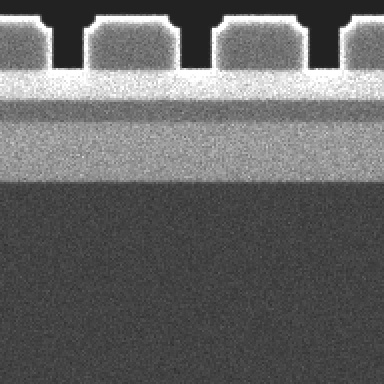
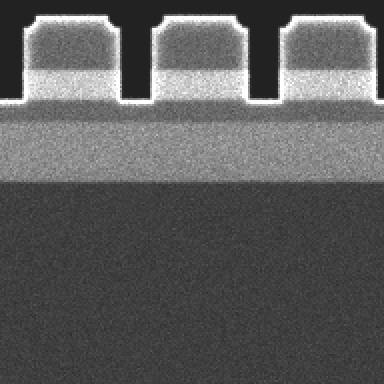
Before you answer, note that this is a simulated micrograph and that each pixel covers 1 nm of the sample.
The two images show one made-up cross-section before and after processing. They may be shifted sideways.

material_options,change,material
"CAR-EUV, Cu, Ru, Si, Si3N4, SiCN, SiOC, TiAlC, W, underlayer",removed,W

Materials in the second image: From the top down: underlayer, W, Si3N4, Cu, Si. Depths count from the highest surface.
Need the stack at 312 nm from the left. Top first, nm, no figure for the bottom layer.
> underlayer 54, W 30, Si3N4 22, Cu 60, Si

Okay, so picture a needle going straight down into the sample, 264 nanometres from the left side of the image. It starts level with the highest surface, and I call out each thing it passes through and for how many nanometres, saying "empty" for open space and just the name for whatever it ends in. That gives empty 84, Si3N4 22, Cu 60, Si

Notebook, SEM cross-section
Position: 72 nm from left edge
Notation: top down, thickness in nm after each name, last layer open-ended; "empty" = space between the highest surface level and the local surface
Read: underlayer 54, W 30, Si3N4 22, Cu 60, Si